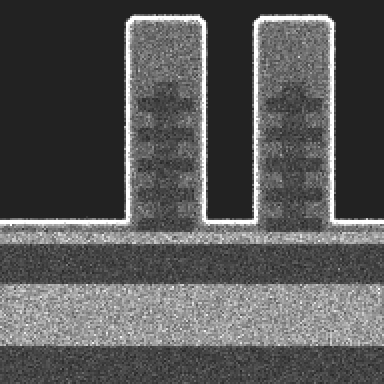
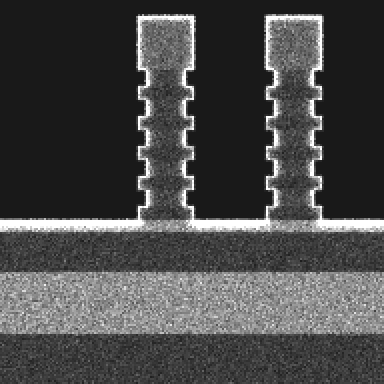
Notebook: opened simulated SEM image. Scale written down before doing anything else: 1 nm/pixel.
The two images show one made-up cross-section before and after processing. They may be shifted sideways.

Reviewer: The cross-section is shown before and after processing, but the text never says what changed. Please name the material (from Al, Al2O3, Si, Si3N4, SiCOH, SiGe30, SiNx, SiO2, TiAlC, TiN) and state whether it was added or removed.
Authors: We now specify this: SiNx, removed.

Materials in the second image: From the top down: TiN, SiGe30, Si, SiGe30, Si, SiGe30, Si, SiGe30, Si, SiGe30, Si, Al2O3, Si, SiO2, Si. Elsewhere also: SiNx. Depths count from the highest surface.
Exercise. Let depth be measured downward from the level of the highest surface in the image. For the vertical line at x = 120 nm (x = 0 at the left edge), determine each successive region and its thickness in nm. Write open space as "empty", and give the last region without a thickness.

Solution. empty 204, Al2O3 12, Si 40, SiO2 62, Si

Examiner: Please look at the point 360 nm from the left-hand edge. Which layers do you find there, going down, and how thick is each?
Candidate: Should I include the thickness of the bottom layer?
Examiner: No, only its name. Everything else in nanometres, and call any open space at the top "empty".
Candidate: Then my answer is empty 204, Al2O3 12, Si 40, SiO2 62, Si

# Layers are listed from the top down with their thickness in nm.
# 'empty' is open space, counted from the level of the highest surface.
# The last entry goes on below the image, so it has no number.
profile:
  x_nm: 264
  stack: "empty 204, Al2O3 12, Si 40, SiO2 62, Si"